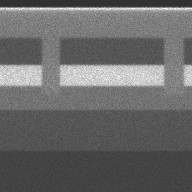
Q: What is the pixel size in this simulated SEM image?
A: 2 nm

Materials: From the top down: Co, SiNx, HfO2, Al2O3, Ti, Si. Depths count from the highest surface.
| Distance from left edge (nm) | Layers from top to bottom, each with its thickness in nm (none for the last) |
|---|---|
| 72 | Co 60, SiNx 54, HfO2 42, Al2O3 48, Ti 82, Si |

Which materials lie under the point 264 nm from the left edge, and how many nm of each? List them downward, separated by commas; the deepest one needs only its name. Co 60, SiNx 54, HfO2 42, Al2O3 48, Ti 82, Si